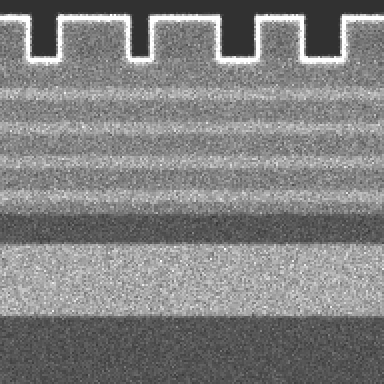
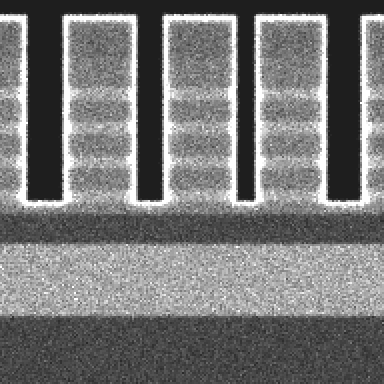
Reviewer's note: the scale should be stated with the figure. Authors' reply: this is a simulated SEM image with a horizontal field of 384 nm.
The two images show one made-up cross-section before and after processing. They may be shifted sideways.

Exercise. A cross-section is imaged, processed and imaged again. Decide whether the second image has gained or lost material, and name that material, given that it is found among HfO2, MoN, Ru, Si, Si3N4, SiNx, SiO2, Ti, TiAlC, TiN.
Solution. removed: Si3N4 and SiO2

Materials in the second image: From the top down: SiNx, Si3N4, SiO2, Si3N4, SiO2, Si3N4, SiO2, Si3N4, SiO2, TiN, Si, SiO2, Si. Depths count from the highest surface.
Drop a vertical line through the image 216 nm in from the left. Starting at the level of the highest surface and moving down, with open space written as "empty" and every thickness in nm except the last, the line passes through SiNx 42, Si3N4 30, SiO2 12, Si3N4 22, SiO2 12, Si3N4 22, SiO2 12, Si3N4 22, SiO2 12, TiN 12, Si 30, SiO2 72, Si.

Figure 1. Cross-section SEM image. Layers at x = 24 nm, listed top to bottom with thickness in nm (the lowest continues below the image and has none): SiNx 42, Si3N4 30, SiO2 12, Si3N4 22, SiO2 12, Si3N4 22, SiO2 12, Si3N4 22, SiO2 12, TiN 12, Si 30, SiO2 72, Si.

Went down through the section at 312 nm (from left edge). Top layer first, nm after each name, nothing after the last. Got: SiNx 42, Si3N4 30, SiO2 12, Si3N4 22, SiO2 12, Si3N4 22, SiO2 12, Si3N4 22, SiO2 12, TiN 12, Si 30, SiO2 72, Si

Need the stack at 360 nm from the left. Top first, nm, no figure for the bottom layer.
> empty 186, TiN 12, Si 30, SiO2 72, Si